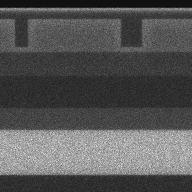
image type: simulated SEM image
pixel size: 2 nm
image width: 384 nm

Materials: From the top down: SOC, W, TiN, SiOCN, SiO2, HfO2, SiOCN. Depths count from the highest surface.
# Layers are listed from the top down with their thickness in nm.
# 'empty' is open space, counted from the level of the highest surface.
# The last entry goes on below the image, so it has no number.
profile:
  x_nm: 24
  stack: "SOC 22, W 66, TiN 48, SiOCN 64, SiO2 44, HfO2 90, SiOCN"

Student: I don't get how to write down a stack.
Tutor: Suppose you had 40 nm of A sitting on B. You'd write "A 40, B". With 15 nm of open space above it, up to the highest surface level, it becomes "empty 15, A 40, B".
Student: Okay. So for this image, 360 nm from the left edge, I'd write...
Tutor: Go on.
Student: SOC 22, W 66, TiN 48, SiOCN 64, SiO2 44, HfO2 90, SiOCN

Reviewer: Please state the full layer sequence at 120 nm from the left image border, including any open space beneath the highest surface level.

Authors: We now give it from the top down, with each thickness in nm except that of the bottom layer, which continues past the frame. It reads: SOC 22, W 66, TiN 48, SiOCN 64, SiO2 44, HfO2 90, SiOCN